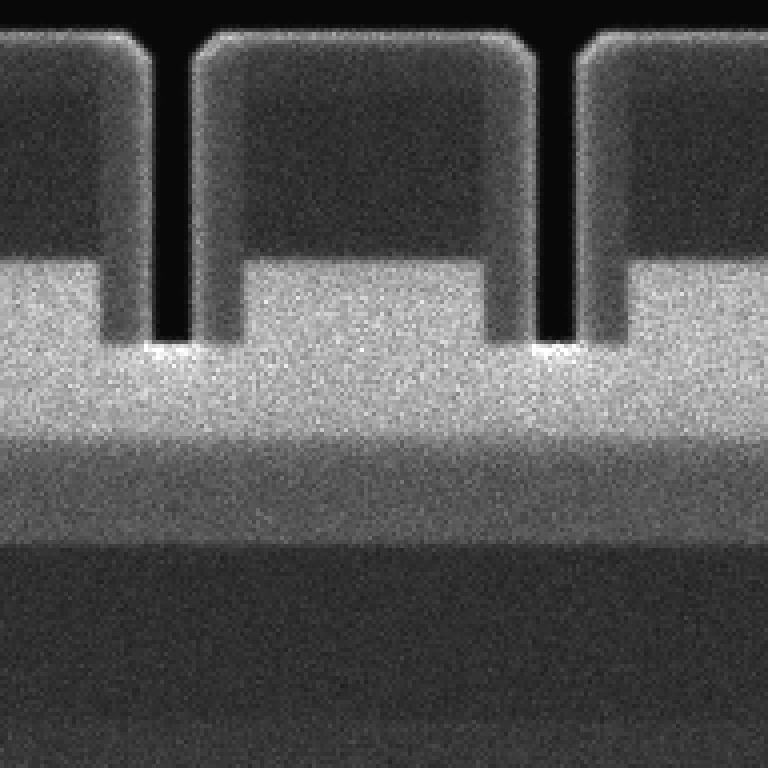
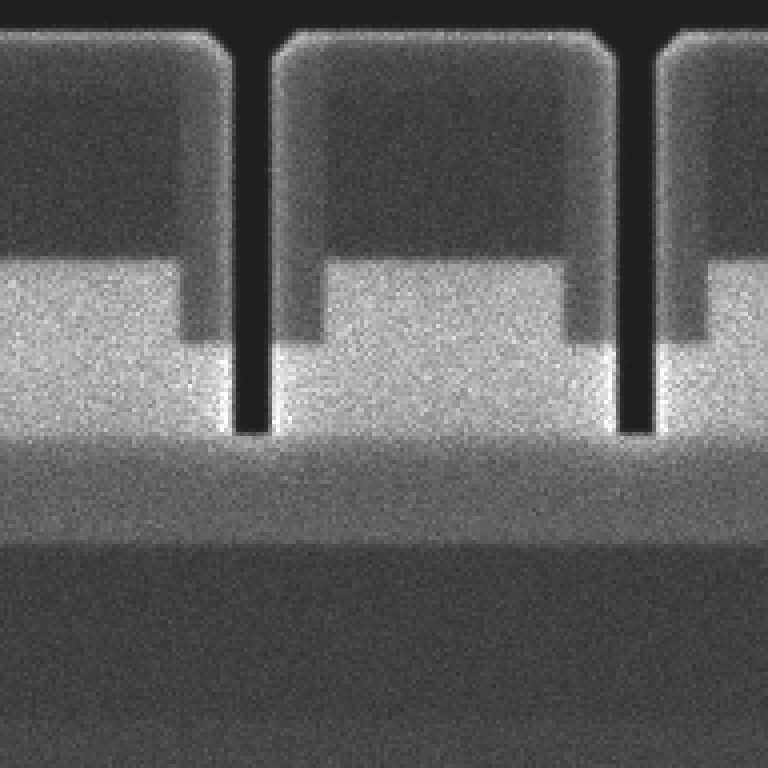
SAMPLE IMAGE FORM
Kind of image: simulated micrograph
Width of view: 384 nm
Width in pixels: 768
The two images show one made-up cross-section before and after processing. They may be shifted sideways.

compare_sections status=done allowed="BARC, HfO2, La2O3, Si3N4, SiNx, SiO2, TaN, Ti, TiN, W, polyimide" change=removed material="HfO2"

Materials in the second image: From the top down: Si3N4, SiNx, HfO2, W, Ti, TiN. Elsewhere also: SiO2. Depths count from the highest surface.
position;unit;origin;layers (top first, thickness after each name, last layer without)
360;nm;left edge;Si3N4 30, SiNx 84, HfO2 88, W 54, Ti 88, TiN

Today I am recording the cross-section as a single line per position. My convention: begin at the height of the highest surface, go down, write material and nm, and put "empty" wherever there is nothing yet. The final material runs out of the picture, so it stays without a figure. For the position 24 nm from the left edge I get Si3N4 30, SiNx 84, HfO2 88, W 54, Ti 88, TiN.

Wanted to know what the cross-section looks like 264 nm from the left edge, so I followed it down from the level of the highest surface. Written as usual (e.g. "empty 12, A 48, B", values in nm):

Si3N4 30, SiNx 84, HfO2 88, W 54, Ti 88, TiN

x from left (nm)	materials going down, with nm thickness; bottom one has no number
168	Si3N4 30, SiNx 84, HfO2 88, W 54, Ti 88, TiN